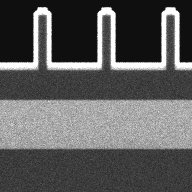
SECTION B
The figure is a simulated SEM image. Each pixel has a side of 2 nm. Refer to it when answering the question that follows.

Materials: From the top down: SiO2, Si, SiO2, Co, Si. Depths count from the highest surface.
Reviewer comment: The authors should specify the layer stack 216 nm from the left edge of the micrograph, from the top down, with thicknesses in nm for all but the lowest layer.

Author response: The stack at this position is SiO2 14, Si 170, SiO2 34, Co 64, Si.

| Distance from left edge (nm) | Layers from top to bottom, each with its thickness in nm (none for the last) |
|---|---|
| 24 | empty 110, SiO2 14, Si 60, SiO2 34, Co 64, Si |